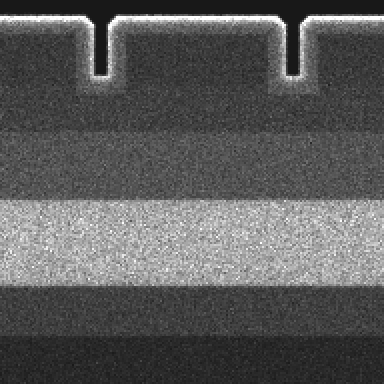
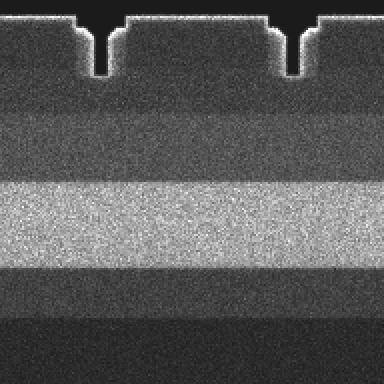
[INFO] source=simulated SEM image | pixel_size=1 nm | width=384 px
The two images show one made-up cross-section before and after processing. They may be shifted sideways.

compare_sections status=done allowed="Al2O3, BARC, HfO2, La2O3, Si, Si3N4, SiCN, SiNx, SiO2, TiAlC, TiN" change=removed material="Al2O3"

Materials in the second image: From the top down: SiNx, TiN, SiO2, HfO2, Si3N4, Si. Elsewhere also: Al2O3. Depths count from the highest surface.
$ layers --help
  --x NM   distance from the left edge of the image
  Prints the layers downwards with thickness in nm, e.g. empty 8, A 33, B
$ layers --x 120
empty 12, Al2O3 48, TiN 38, SiO2 68, HfO2 86, Si3N4 50, Si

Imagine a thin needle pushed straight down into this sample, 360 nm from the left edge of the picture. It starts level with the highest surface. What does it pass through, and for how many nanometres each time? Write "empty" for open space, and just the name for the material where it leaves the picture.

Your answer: SiNx 52, TiN 46, SiO2 68, HfO2 86, Si3N4 50, Si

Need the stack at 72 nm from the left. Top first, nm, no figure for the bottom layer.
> SiNx 52, TiN 46, SiO2 68, HfO2 86, Si3N4 50, Si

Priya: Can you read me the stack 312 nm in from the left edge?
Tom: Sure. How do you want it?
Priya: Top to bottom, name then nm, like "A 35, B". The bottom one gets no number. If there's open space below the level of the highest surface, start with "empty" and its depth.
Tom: empty 12, Al2O3 48, TiN 38, SiO2 68, HfO2 86, Si3N4 50, Si